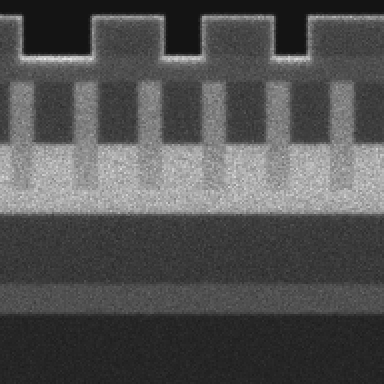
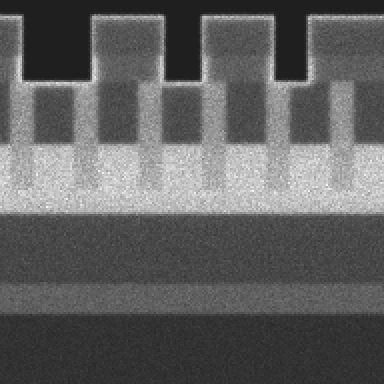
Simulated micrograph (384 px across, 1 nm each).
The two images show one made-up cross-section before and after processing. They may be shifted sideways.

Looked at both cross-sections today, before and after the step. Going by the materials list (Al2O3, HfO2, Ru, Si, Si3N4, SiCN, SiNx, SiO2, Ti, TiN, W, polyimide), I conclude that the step removed SiO2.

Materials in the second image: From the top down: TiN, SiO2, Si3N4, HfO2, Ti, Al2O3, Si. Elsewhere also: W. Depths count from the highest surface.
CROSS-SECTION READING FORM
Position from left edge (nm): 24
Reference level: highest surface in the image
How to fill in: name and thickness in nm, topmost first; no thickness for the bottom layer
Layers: empty 66, W 108, HfO2 24, Ti 70, Al2O3 30, Si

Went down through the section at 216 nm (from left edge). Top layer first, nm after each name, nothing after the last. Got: TiN 40, SiO2 26, W 108, HfO2 24, Ti 70, Al2O3 30, Si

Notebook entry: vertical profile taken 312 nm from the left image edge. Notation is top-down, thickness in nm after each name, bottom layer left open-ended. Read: TiN 40, SiO2 26, Si3N4 62, HfO2 70, Ti 70, Al2O3 30, Si